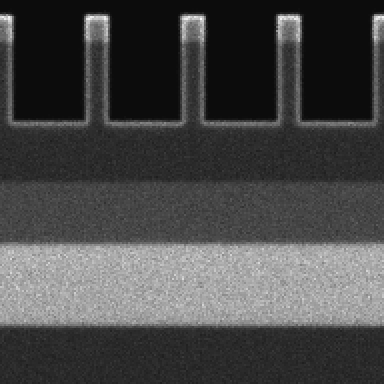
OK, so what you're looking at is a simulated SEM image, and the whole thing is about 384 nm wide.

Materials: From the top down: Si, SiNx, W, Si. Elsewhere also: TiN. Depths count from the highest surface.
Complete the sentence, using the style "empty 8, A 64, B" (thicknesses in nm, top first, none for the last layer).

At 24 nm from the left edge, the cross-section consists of empty 106, Si 60, SiNx 62, W 82, Si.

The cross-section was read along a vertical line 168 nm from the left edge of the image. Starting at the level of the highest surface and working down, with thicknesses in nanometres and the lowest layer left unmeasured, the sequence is empty 106, Si 60, SiNx 62, W 82, Si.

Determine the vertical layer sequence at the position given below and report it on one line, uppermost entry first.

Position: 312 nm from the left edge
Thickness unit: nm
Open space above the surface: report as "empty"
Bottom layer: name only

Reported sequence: empty 106, Si 60, SiNx 62, W 82, Si